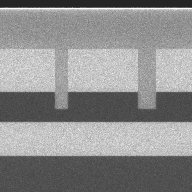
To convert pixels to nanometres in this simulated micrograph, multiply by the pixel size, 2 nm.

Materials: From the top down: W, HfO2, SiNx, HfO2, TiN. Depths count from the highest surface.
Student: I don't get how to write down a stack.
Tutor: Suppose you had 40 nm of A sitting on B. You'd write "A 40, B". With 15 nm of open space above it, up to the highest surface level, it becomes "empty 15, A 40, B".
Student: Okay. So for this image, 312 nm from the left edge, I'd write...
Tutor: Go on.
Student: W 82, HfO2 86, SiNx 60, HfO2 68, TiN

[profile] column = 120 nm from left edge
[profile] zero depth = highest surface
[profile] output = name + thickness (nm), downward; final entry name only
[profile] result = W 202, SiNx 26, HfO2 68, TiN